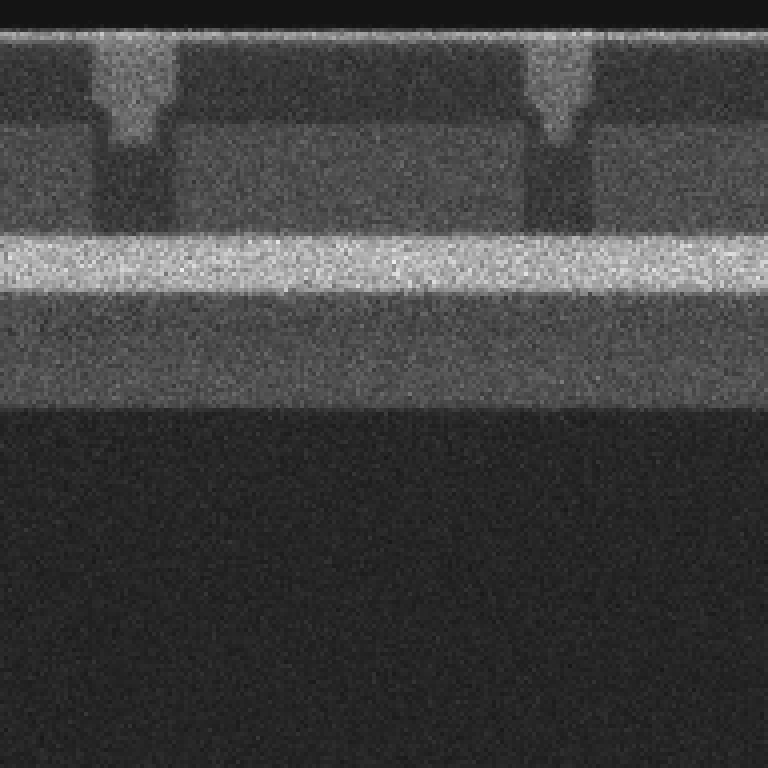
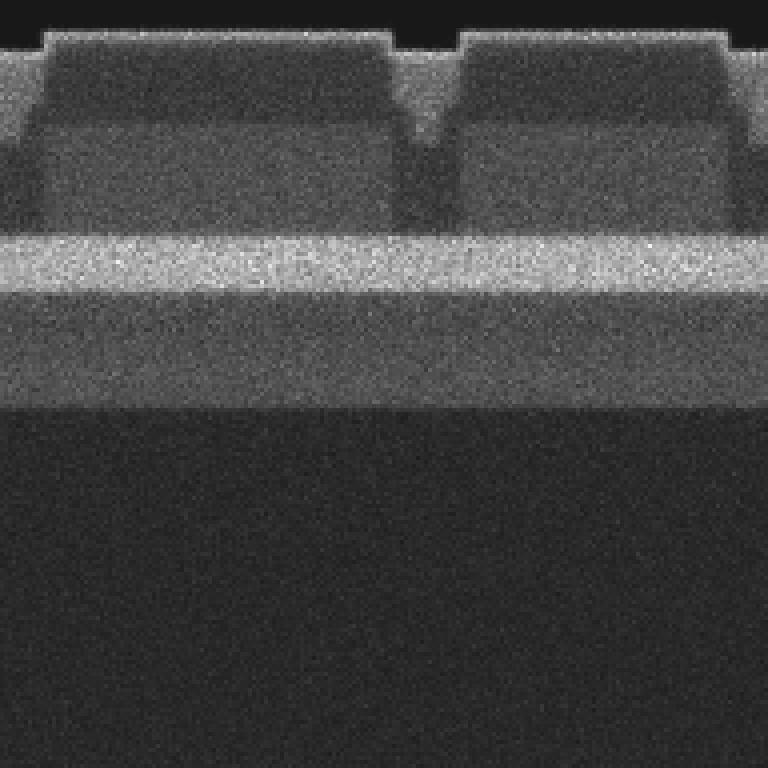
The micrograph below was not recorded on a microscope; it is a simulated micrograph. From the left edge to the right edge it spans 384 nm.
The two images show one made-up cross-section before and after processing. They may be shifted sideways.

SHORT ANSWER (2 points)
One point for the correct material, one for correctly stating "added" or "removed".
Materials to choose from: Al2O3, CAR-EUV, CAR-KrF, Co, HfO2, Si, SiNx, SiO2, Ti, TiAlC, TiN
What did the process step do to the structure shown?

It removed Co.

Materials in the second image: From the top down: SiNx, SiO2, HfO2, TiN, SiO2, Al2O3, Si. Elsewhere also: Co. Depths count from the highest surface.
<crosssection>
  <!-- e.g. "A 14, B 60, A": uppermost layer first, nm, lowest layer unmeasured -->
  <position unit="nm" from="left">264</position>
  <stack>SiNx 46, SiO2 56, HfO2 28, TiN 22, SiO2 12, Al2O3 24, Si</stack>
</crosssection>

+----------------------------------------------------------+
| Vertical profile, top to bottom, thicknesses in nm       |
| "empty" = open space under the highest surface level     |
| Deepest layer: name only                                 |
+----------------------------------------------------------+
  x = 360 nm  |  SiNx 46, SiO2 56, HfO2 28, TiN 22, SiO2 12, Al2O3 24, Si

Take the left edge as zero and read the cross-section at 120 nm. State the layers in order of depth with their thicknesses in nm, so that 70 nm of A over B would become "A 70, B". SiNx 46, SiO2 56, HfO2 28, TiN 22, SiO2 12, Al2O3 24, Si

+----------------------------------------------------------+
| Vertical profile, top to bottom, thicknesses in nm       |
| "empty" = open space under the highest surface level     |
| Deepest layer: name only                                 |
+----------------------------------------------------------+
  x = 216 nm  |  empty 10, Co 46, SiNx 46, HfO2 28, TiN 22, SiO2 12, Al2O3 24, Si